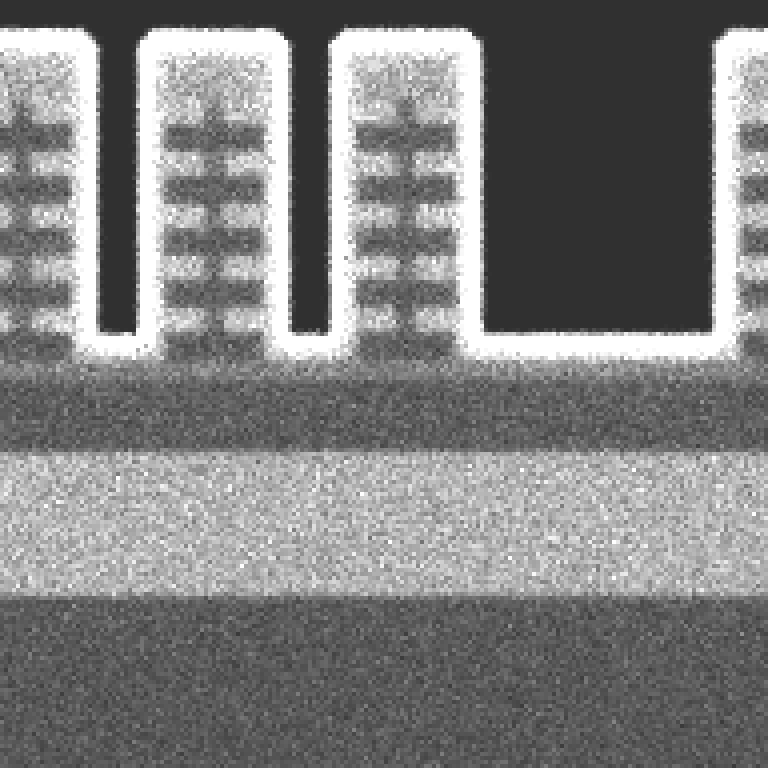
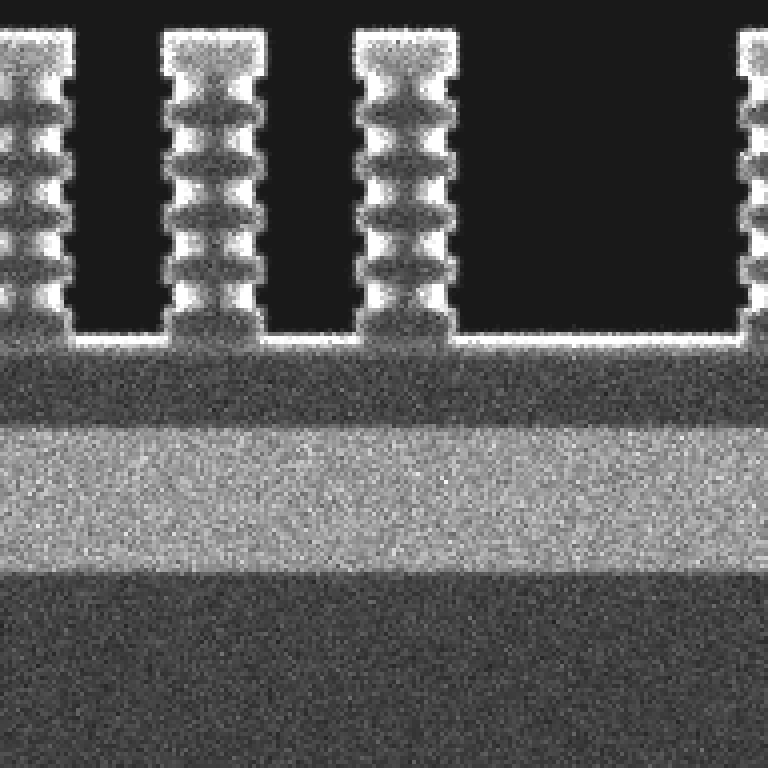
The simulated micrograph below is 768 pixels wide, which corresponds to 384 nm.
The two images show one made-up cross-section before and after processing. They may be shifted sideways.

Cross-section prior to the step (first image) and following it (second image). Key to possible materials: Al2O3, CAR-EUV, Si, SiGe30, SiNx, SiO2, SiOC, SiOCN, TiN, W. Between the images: Al2O3 was removed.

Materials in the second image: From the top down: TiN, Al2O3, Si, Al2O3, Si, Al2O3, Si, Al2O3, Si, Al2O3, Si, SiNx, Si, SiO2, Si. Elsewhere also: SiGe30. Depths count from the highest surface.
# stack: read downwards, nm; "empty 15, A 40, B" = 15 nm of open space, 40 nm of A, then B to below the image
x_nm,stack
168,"empty 152, SiNx 10, Si 36, SiO2 72, Si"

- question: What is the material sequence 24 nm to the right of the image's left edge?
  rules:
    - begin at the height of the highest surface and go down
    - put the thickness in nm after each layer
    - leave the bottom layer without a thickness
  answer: TiN 22, Al2O3 12, Si 14, Al2O3 12, Si 14, Al2O3 12, Si 14, Al2O3 12, Si 14, Al2O3 12, Si 14, SiNx 10, Si 36, SiO2 72, Si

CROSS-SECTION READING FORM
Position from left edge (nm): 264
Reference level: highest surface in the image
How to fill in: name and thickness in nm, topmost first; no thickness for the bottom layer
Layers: empty 152, SiNx 10, Si 36, SiO2 72, Si